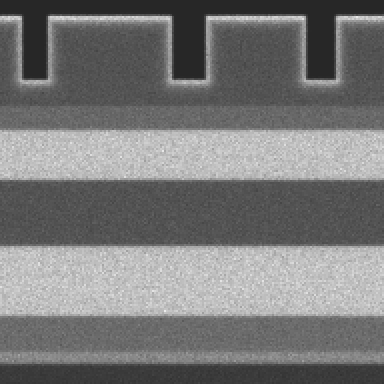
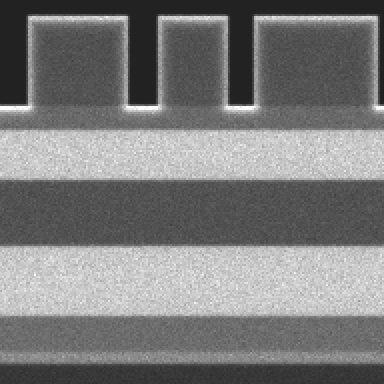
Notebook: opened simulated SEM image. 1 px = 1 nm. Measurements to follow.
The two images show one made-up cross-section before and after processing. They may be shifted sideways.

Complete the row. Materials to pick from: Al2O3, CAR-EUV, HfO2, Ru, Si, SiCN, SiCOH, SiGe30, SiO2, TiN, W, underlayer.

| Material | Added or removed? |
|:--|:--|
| underlayer | removed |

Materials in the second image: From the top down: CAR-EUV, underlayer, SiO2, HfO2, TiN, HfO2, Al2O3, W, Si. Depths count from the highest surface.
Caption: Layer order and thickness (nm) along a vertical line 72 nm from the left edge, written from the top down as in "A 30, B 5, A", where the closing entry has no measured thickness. CAR-EUV 64, underlayer 26, SiO2 24, HfO2 50, TiN 66, HfO2 70, Al2O3 36, W 12, Si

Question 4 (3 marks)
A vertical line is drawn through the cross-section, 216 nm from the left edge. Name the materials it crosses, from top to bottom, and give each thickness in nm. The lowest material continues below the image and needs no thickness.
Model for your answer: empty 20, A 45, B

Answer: CAR-EUV 64, underlayer 26, SiO2 24, HfO2 50, TiN 66, HfO2 70, Al2O3 36, W 12, Si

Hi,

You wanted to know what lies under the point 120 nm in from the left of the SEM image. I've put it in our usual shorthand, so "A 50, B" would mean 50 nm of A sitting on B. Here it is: CAR-EUV 64, underlayer 26, SiO2 24, HfO2 50, TiN 66, HfO2 70, Al2O3 36, W 12, Si